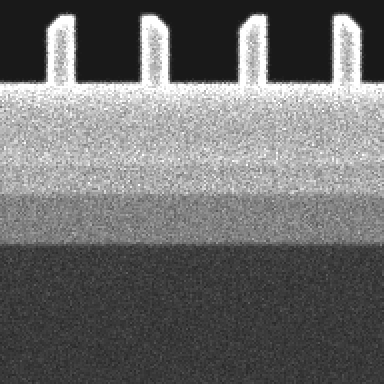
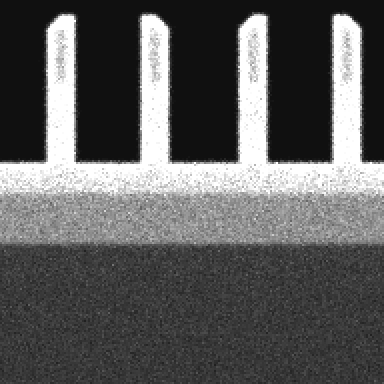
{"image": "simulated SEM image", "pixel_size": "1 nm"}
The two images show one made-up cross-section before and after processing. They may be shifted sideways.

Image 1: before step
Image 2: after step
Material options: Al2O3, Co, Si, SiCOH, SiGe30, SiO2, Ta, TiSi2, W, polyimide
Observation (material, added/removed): W, removed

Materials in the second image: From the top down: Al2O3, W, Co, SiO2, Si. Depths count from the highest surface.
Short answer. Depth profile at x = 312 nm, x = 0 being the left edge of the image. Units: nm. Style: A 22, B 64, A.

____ empty 148, Co 30, SiO2 50, Si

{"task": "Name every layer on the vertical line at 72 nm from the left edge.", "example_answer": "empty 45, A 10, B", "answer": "Al2O3 68, W 80, Co 30, SiO2 50, Si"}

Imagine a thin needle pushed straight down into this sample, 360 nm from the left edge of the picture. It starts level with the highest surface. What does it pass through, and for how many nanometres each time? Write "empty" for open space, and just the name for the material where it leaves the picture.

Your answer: empty 148, Co 30, SiO2 50, Si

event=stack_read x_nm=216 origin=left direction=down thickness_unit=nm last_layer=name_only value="empty 148, Co 30, SiO2 50, Si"